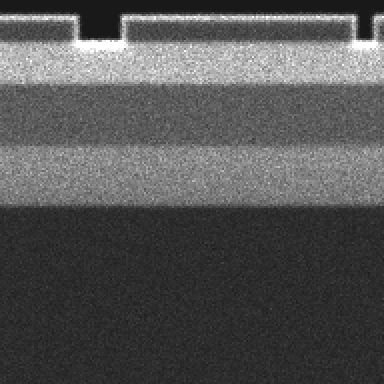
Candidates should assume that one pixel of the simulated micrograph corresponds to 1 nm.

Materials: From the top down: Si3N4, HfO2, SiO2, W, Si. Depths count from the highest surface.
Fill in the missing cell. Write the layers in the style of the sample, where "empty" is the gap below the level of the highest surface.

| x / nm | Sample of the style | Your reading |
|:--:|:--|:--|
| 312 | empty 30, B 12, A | Si3N4 26, HfO2 42, SiO2 62, W 60, Si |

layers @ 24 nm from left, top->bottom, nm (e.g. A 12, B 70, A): Si3N4 26, HfO2 42, SiO2 62, W 60, Si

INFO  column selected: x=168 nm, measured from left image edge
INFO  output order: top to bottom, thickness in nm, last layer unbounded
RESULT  Si3N4 26, HfO2 42, SiO2 62, W 60, Si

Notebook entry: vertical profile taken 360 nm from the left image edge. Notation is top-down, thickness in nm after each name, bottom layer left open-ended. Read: empty 26, HfO2 42, SiO2 62, W 60, Si